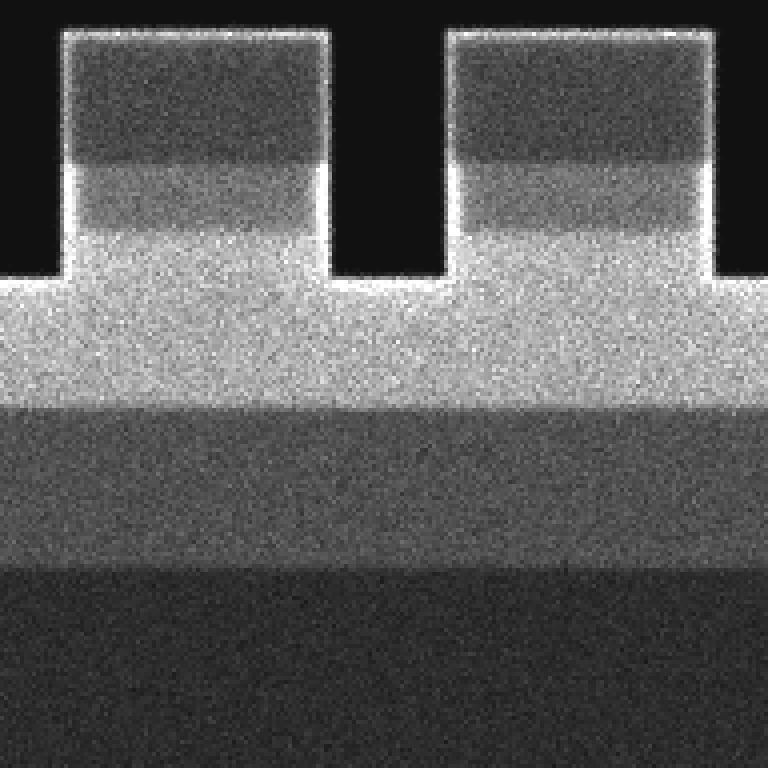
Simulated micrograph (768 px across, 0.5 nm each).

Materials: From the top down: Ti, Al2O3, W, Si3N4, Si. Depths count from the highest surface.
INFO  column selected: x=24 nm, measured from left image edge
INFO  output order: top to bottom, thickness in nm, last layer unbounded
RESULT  empty 124, W 64, Si3N4 80, Si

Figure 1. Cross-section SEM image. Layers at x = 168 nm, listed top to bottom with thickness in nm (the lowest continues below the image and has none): empty 124, W 64, Si3N4 80, Si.